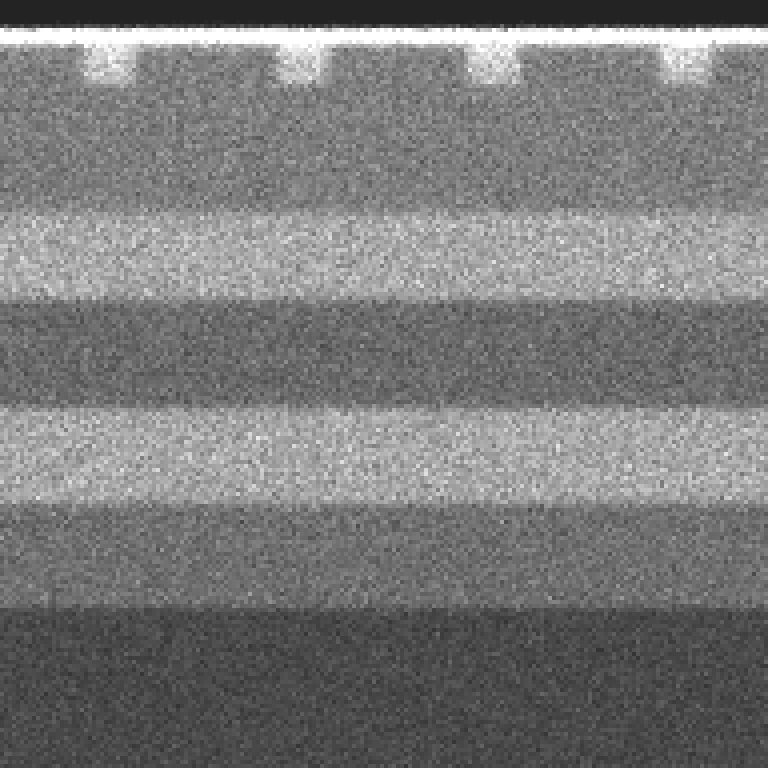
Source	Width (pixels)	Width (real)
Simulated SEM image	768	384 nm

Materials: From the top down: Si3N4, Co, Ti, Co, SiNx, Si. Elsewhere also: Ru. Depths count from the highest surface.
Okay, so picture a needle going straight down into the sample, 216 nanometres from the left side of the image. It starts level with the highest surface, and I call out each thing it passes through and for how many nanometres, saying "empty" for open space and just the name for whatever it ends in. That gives Si3N4 90, Co 44, Ti 54, Co 48, SiNx 52, Si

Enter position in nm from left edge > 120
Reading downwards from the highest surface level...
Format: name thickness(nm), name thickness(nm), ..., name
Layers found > Si3N4 90, Co 44, Ti 54, Co 48, SiNx 52, Si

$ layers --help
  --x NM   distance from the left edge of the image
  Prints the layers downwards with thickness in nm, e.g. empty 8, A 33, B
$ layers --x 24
Si3N4 90, Co 44, Ti 54, Co 48, SiNx 52, Si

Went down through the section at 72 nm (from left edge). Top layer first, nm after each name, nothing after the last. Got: Si3N4 90, Co 44, Ti 54, Co 48, SiNx 52, Si